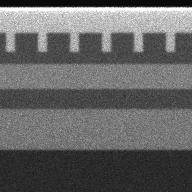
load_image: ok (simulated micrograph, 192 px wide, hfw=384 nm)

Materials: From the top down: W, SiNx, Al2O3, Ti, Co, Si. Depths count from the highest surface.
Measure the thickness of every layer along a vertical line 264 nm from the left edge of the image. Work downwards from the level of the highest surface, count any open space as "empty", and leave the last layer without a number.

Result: W 50, SiNx 62, Al2O3 50, Ti 40, Co 82, Si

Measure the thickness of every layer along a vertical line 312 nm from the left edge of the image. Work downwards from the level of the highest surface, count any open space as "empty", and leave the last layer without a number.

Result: W 50, SiNx 62, Al2O3 50, Ti 40, Co 82, Si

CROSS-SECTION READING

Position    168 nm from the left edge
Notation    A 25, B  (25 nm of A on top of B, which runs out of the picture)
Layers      W 50, SiNx 62, Al2O3 50, Ti 40, Co 82, Si